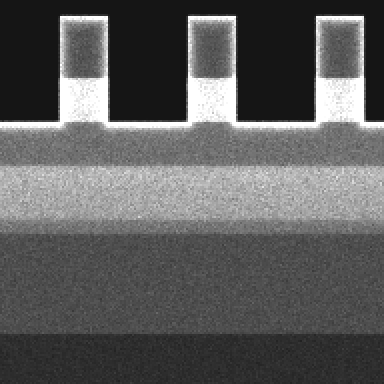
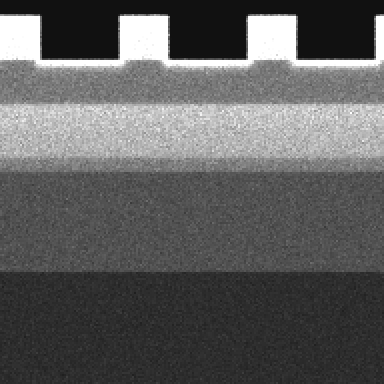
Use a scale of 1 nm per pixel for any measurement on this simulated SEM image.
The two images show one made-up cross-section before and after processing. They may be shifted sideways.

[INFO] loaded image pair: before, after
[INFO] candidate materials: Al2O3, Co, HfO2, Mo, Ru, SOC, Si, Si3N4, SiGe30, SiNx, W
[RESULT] removed SOC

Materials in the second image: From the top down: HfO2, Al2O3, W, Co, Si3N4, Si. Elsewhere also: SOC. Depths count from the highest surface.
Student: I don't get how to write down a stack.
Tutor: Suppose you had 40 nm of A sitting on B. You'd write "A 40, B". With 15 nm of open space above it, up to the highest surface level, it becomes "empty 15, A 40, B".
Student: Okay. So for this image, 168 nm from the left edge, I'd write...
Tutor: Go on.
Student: empty 44, Al2O3 44, W 54, Co 14, Si3N4 100, Si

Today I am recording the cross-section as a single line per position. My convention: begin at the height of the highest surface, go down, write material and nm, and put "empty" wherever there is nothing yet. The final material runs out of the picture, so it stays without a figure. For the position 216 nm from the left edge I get empty 44, Al2O3 44, W 54, Co 14, Si3N4 100, Si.